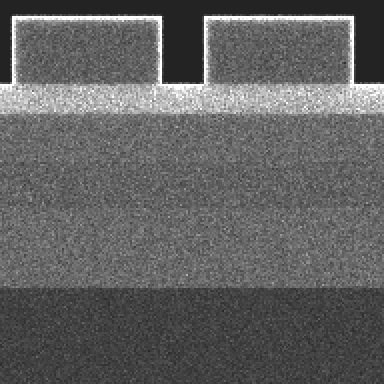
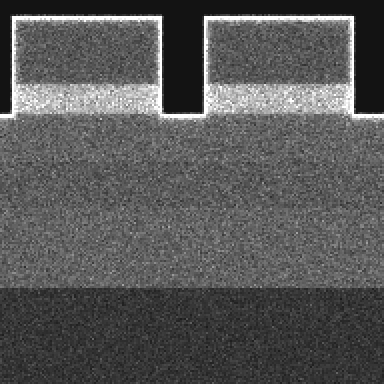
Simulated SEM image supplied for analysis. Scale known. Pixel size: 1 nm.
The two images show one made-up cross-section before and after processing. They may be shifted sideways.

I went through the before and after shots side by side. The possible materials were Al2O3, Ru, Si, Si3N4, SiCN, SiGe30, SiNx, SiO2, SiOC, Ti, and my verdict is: removed, Ru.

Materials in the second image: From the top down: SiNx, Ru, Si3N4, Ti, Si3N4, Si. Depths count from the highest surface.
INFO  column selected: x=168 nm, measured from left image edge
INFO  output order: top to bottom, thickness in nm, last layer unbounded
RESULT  empty 98, Si3N4 48, Ti 46, Si3N4 80, Si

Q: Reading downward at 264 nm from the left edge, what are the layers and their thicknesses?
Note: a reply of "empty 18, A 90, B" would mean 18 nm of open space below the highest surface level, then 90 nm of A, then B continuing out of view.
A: SiNx 68, Ru 30, Si3N4 48, Ti 46, Si3N4 80, Si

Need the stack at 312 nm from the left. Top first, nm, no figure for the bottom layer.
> SiNx 68, Ru 30, Si3N4 48, Ti 46, Si3N4 80, Si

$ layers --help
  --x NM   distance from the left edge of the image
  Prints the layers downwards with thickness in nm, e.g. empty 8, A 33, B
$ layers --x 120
SiNx 68, Ru 30, Si3N4 48, Ti 46, Si3N4 80, Si